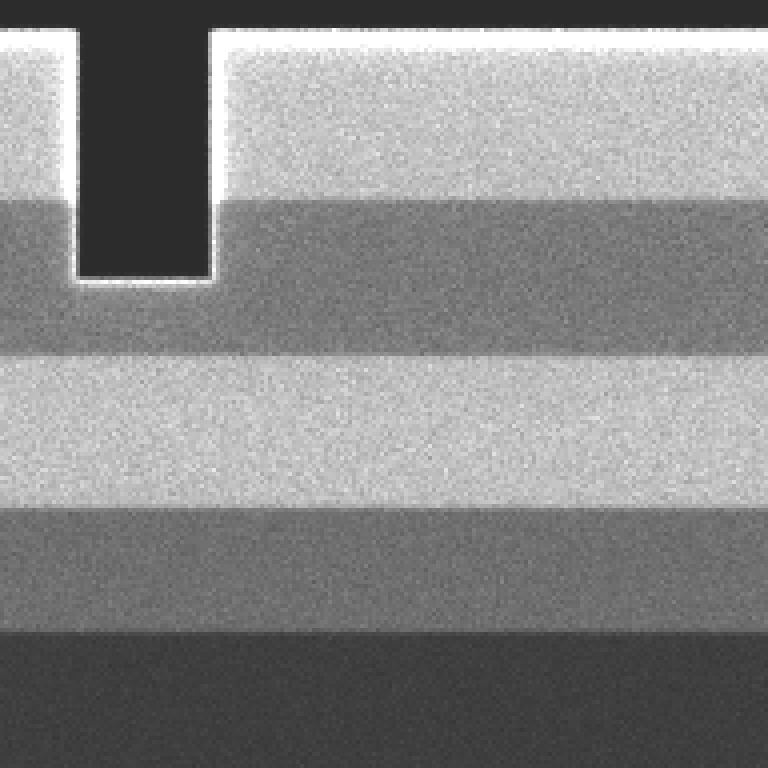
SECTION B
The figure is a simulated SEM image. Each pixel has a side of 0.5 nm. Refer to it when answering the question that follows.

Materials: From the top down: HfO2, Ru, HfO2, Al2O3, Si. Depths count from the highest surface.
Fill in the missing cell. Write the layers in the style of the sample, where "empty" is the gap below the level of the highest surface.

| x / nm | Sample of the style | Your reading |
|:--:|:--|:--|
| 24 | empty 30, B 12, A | HfO2 84, Ru 78, HfO2 76, Al2O3 62, Si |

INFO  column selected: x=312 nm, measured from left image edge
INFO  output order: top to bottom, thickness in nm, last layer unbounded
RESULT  HfO2 84, Ru 78, HfO2 76, Al2O3 62, Si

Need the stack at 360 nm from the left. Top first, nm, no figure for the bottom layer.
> HfO2 84, Ru 78, HfO2 76, Al2O3 62, Si